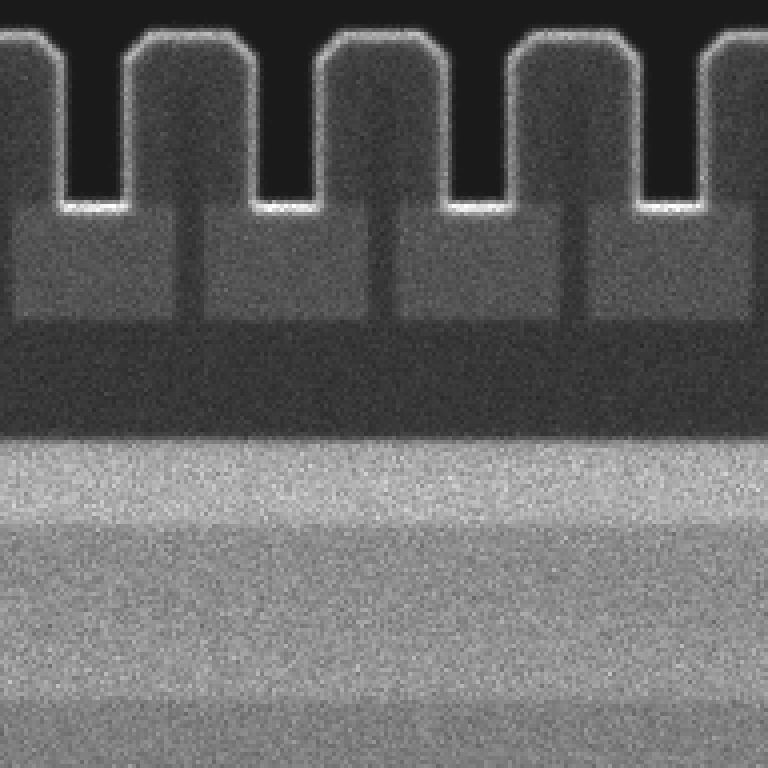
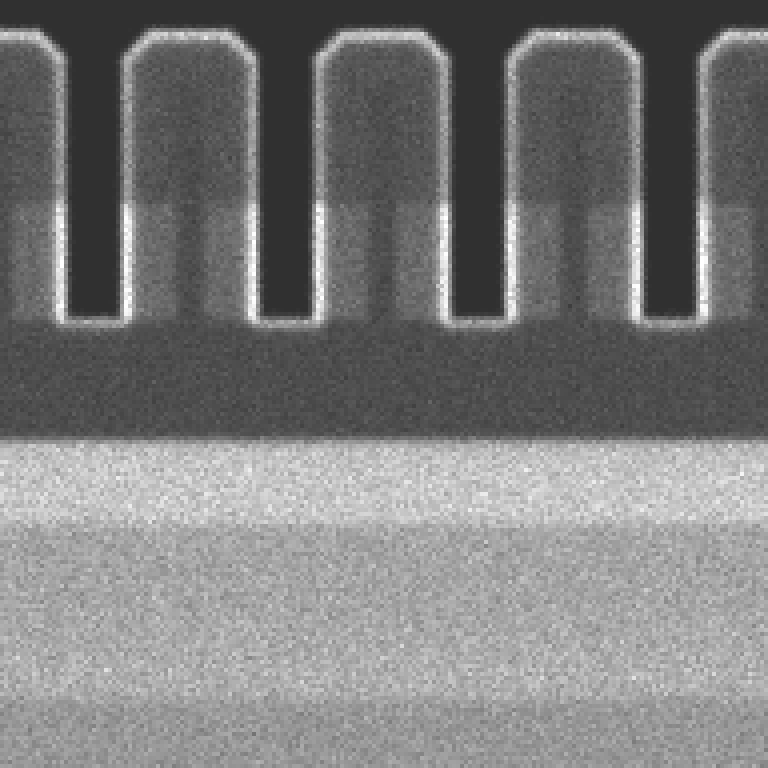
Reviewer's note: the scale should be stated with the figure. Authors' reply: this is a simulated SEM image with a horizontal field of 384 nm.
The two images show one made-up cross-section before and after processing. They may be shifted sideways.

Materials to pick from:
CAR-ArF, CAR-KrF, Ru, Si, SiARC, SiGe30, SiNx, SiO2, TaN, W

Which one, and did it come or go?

SiNx - removed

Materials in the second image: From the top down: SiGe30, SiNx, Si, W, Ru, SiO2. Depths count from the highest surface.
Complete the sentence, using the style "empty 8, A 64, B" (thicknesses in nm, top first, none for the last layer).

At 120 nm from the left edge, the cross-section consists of empty 6, SiGe30 80, SiNx 58, Si 60, W 42, Ru 88, SiO2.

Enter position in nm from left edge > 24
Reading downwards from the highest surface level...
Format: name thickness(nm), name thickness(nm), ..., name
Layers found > empty 6, SiGe30 80, SiNx 58, Si 60, W 42, Ru 88, SiO2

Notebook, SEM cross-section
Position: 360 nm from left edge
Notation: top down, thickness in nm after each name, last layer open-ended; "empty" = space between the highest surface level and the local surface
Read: empty 2, SiGe30 84, SiNx 58, Si 60, W 42, Ru 88, SiO2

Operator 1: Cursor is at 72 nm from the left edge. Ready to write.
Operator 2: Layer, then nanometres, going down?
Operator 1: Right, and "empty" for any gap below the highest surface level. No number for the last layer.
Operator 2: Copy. empty 2, SiGe30 84, SiNx 58, Si 60, W 42, Ru 88, SiO2